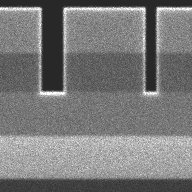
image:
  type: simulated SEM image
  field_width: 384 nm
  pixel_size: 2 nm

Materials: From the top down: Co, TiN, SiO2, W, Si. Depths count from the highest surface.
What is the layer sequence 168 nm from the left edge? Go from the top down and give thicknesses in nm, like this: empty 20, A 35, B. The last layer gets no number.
Co 90, TiN 78, SiO2 88, W 86, Si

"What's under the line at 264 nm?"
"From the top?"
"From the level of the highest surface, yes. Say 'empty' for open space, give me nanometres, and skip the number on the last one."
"Co 90, TiN 78, SiO2 88, W 86, Si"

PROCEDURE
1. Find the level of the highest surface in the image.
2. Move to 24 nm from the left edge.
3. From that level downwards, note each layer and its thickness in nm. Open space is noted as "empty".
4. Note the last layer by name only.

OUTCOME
Co 90, TiN 78, SiO2 88, W 86, Si